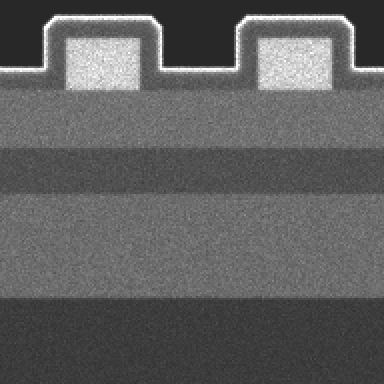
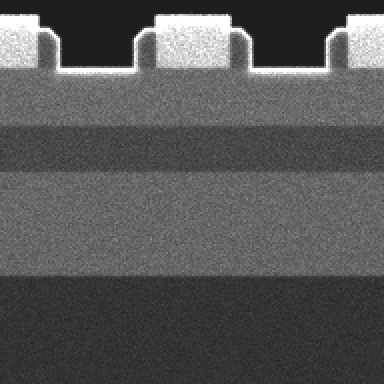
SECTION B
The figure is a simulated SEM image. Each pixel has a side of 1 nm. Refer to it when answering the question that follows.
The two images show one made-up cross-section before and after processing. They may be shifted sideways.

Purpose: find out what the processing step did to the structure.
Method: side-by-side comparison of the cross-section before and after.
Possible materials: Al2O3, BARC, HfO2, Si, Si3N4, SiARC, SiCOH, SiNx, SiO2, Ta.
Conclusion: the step removed Si3N4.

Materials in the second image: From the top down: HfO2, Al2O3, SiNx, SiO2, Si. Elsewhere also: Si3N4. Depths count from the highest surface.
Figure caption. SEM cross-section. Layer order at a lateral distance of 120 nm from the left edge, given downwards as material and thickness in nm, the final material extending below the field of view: empty 52, Al2O3 58, SiNx 46, SiO2 104, Si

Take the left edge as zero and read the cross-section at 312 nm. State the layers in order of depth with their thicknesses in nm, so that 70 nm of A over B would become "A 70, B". empty 52, Al2O3 58, SiNx 46, SiO2 104, Si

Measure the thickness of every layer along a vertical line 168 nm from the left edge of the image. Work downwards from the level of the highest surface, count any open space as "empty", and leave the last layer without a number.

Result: HfO2 52, Al2O3 58, SiNx 46, SiO2 104, Si